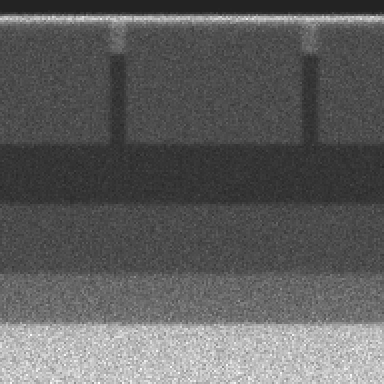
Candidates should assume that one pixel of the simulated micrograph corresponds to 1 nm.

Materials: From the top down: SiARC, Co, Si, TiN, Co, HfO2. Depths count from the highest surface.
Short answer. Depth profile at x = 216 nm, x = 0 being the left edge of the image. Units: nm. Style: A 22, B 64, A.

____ SiARC 128, Si 60, TiN 70, Co 50, HfO2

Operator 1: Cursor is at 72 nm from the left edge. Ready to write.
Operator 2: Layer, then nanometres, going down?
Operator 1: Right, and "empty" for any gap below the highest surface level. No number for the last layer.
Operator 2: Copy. SiARC 128, Si 60, TiN 70, Co 50, HfO2